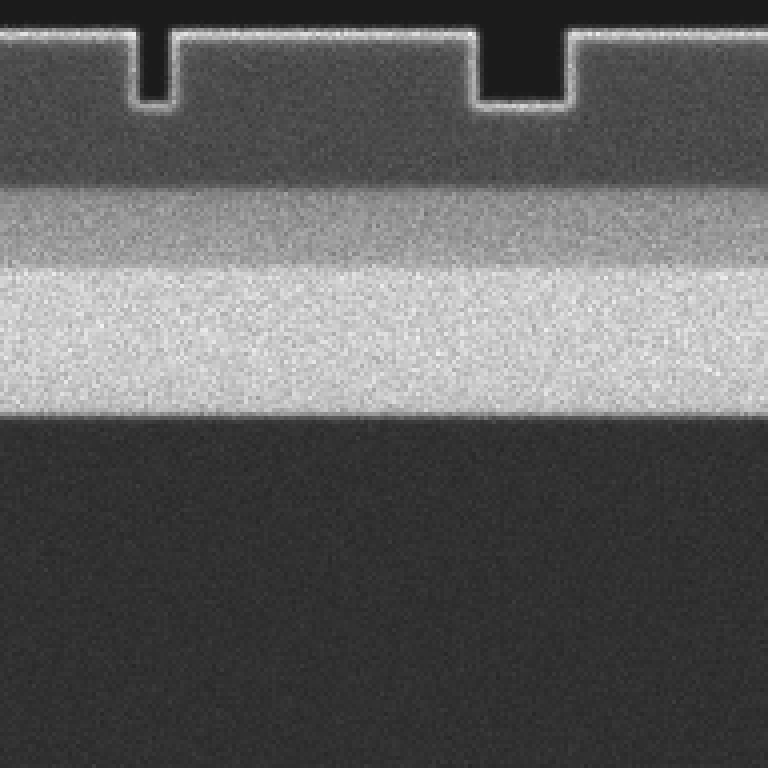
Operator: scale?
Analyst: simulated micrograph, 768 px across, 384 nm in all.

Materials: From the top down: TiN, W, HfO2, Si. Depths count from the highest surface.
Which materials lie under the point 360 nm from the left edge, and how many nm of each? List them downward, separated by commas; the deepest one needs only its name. TiN 78, W 40, HfO2 74, Si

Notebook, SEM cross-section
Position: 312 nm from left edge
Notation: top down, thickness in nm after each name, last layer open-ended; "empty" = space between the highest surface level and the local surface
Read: TiN 78, W 40, HfO2 74, Si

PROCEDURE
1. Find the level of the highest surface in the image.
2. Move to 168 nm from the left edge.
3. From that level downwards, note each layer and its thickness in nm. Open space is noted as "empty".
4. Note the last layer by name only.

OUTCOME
TiN 78, W 40, HfO2 74, Si